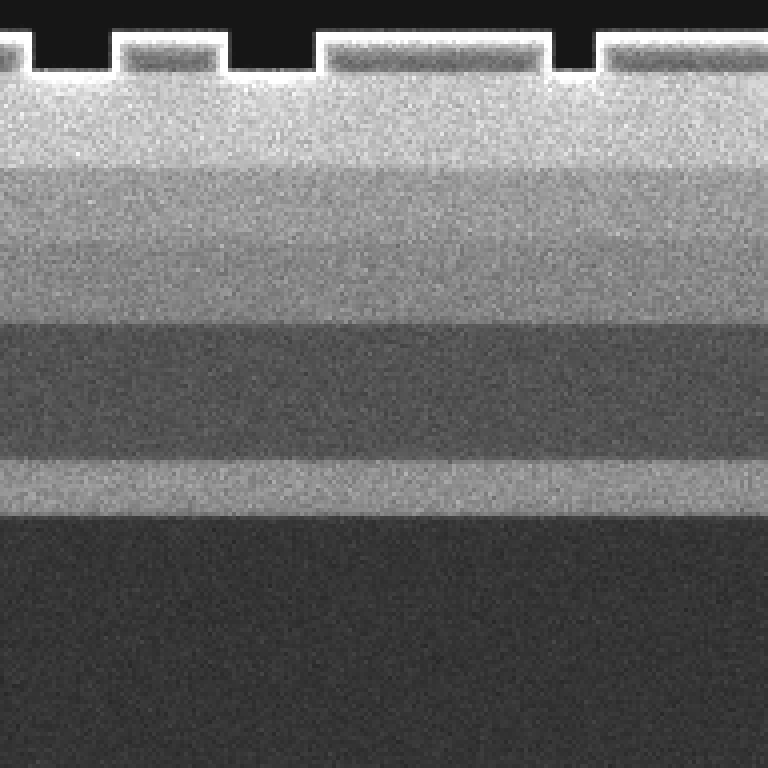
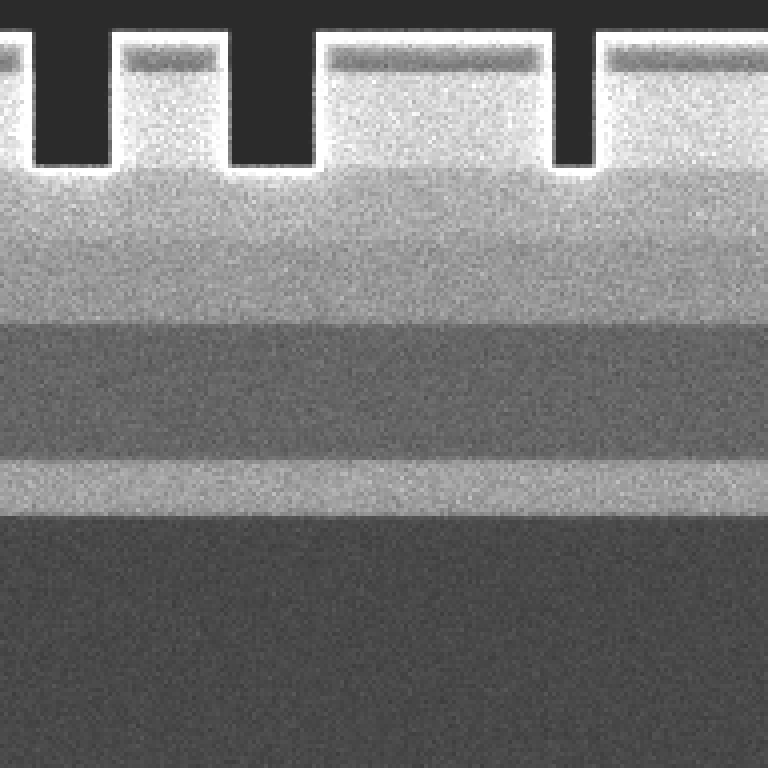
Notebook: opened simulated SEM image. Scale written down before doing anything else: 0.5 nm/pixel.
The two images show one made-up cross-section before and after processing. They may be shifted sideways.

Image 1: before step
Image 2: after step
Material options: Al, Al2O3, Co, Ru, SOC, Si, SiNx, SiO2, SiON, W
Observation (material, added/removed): W, removed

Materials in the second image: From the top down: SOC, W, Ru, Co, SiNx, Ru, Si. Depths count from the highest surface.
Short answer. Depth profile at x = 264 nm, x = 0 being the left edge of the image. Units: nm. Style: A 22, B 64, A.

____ SOC 20, W 48, Ru 36, Co 42, SiNx 68, Ru 28, Si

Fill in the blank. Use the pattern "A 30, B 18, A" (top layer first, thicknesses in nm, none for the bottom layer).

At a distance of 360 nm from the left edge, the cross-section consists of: SOC 20, W 48, Ru 36, Co 42, SiNx 68, Ru 28, Si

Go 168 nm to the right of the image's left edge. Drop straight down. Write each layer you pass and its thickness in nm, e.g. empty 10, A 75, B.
SOC 20, W 48, Ru 36, Co 42, SiNx 68, Ru 28, Si